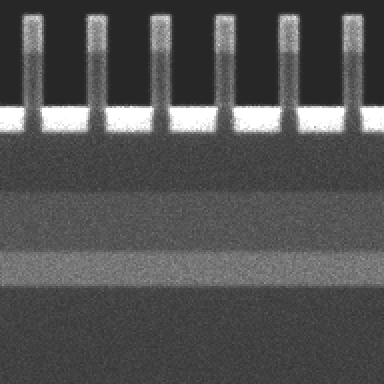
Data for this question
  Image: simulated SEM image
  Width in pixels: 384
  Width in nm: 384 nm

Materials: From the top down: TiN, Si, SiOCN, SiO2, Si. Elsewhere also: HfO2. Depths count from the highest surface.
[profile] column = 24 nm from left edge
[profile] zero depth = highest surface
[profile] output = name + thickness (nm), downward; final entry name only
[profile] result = TiN 36, Si 140, SiOCN 60, SiO2 34, Si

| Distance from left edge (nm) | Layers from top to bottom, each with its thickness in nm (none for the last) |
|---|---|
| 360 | TiN 36, Si 140, SiOCN 60, SiO2 34, Si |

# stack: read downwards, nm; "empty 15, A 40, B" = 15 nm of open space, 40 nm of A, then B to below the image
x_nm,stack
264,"empty 92, HfO2 24, Si 60, SiOCN 60, SiO2 34, Si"